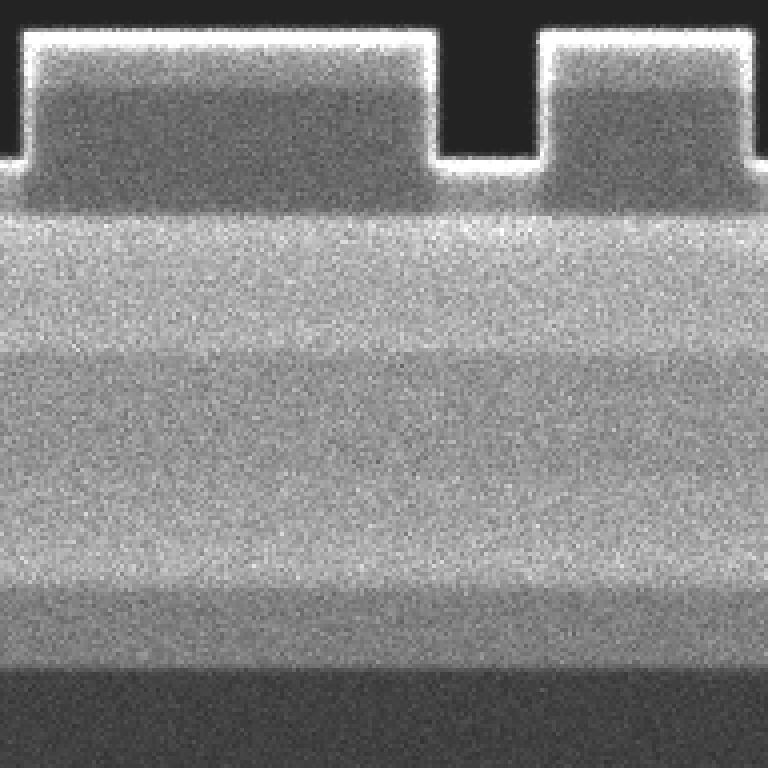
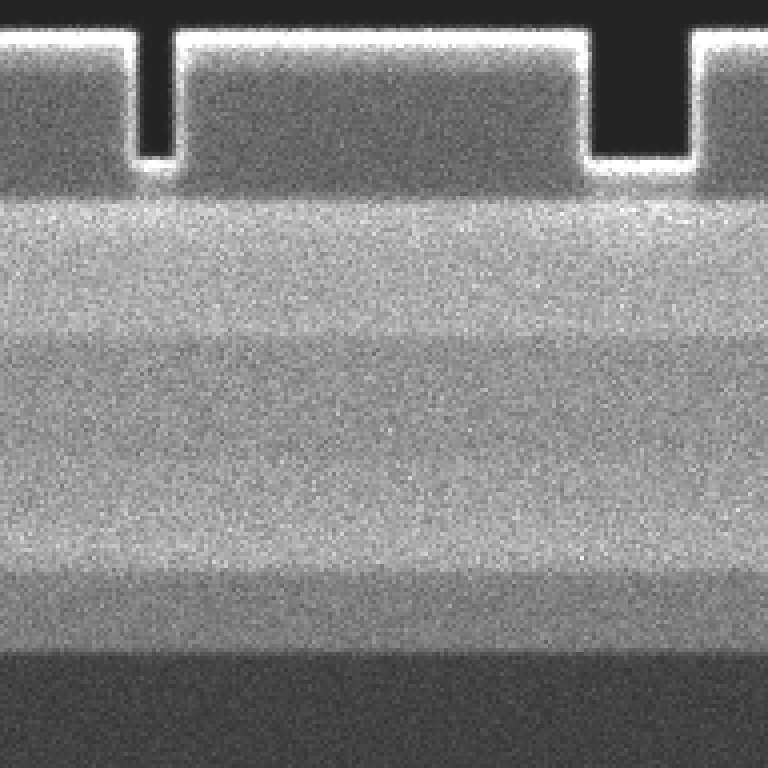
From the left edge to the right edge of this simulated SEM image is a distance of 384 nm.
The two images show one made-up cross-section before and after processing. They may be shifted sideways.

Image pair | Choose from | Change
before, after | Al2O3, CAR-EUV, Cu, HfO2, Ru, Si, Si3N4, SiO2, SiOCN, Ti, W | Al2O3 (removed)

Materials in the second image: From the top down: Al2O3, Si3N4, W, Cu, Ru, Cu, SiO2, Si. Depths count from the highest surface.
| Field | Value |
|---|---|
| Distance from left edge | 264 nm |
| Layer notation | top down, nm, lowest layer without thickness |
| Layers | Al2O3 20, Si3N4 64, W 68, Cu 62, Ru 48, Cu 8, SiO2 40, Si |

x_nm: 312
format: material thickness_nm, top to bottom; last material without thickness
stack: empty 64, Al2O3 20, W 68, Cu 62, Ru 48, Cu 8, SiO2 40, Si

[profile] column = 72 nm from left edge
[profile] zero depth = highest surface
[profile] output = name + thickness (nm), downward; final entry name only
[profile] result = empty 64, Al2O3 20, W 68, Cu 62, Ru 48, Cu 8, SiO2 40, Si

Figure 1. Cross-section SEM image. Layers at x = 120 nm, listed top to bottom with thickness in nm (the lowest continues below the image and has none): Al2O3 20, Si3N4 64, W 68, Cu 62, Ru 48, Cu 8, SiO2 40, Si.